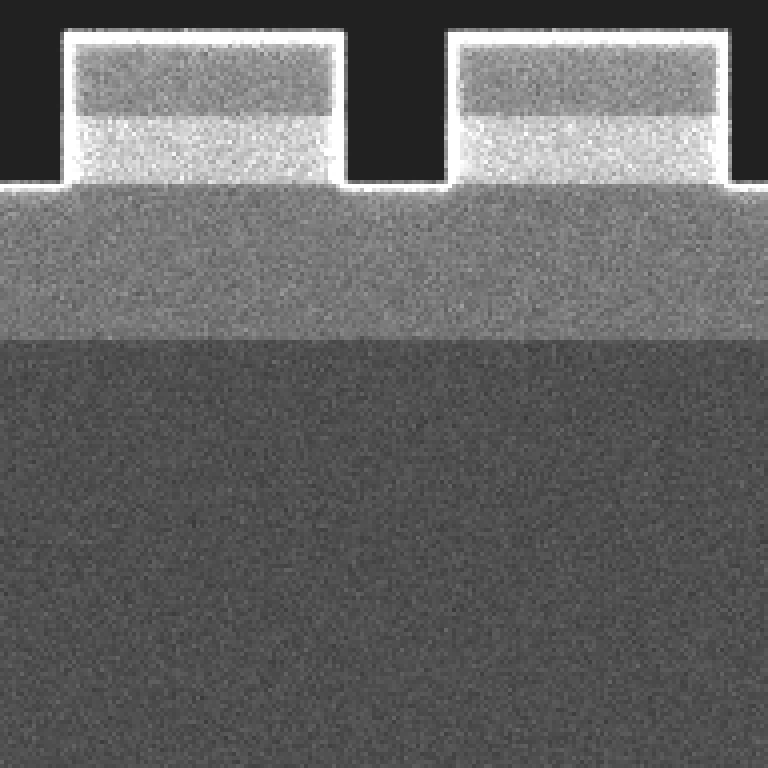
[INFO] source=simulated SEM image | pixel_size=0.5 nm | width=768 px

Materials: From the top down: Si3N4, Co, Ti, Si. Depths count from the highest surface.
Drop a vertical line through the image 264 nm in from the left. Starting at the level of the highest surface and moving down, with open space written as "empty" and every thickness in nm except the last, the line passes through Si3N4 42, Co 34, Ti 78, Si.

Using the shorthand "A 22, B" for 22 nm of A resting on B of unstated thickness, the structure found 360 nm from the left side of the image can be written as Si3N4 42, Co 34, Ti 78, Si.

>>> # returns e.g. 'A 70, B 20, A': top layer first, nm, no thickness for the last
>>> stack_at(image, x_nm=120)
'Si3N4 42, Co 34, Ti 78, Si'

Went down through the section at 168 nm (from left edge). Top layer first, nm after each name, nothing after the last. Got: Si3N4 42, Co 34, Ti 78, Si